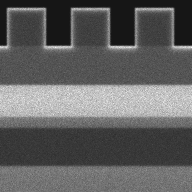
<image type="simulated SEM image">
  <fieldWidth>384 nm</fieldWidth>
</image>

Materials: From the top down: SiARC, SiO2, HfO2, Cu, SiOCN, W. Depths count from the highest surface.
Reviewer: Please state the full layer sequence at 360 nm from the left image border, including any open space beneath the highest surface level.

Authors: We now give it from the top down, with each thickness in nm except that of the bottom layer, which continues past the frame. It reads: empty 76, SiO2 78, HfO2 64, Cu 22, SiOCN 76, W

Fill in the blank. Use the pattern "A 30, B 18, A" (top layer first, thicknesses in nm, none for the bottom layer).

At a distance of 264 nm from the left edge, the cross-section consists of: empty 76, SiO2 78, HfO2 64, Cu 22, SiOCN 76, W